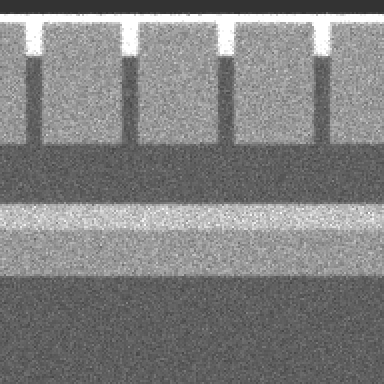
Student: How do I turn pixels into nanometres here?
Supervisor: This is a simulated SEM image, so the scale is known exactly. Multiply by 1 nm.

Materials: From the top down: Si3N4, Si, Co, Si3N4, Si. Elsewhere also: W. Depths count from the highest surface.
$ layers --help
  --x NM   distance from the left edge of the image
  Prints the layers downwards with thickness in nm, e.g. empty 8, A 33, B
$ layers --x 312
Si3N4 128, Si 60, Co 26, Si3N4 46, Si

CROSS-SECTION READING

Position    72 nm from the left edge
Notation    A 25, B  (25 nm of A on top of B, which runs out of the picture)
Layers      Si3N4 128, Si 60, Co 26, Si3N4 46, Si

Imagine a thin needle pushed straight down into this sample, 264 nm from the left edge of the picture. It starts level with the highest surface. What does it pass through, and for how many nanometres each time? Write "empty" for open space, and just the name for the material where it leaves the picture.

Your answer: Si3N4 128, Si 60, Co 26, Si3N4 46, Si